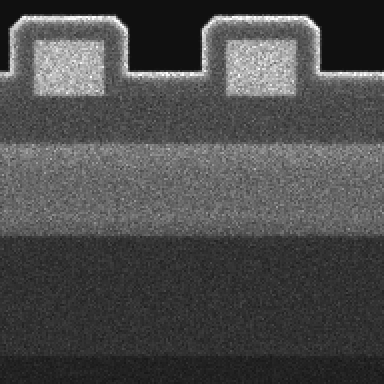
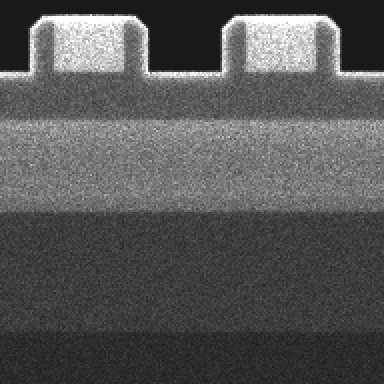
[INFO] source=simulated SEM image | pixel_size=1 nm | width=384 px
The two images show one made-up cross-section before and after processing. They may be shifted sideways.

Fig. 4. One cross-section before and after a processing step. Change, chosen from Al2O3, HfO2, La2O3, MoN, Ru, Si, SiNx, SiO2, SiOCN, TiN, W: Al2O3 removed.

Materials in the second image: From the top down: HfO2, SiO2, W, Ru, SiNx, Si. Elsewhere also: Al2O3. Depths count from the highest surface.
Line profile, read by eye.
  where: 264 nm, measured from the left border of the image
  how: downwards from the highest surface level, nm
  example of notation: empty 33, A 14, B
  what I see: HfO2 56, SiO2 48, W 78, Ru 14, SiNx 120, Si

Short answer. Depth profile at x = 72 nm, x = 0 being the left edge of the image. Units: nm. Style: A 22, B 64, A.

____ HfO2 56, SiO2 48, W 78, Ru 14, SiNx 120, Si